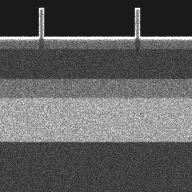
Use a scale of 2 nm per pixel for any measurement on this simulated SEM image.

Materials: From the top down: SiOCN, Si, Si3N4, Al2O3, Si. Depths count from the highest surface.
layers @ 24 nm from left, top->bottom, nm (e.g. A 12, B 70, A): empty 58, SiOCN 24, Si 60, Si3N4 38, Al2O3 88, Si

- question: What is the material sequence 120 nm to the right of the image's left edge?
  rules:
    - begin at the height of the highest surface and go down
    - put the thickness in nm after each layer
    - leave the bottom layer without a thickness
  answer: empty 58, SiOCN 24, Si 60, Si3N4 38, Al2O3 88, Si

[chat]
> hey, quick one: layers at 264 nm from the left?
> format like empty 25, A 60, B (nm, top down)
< empty 58, SiOCN 24, Si 60, Si3N4 38, Al2O3 88, Si